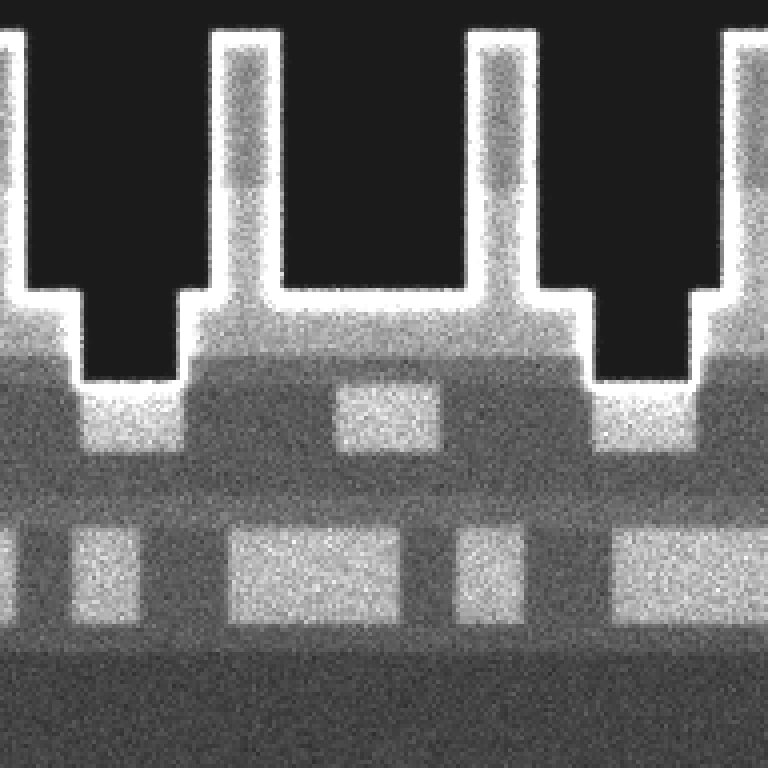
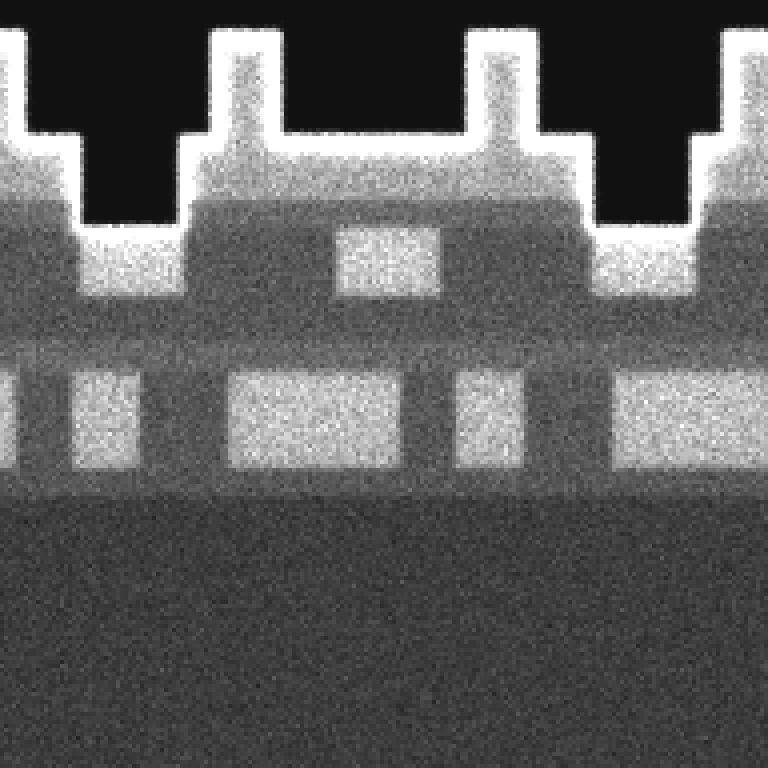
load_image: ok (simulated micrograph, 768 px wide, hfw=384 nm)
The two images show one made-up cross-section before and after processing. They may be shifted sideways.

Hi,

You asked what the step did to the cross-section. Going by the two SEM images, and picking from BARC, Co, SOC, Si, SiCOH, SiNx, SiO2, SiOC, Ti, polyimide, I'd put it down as SOC, removed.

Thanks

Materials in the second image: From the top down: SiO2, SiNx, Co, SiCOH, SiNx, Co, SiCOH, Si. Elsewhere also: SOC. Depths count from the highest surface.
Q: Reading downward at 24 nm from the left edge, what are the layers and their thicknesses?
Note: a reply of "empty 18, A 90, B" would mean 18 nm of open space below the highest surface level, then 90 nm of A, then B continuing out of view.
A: empty 52, SiO2 32, SiNx 14, SiCOH 56, SiNx 16, SiCOH 62, Si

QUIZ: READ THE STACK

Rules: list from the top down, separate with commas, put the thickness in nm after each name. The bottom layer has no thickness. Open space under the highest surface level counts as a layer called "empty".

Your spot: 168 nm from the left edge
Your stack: empty 52, SiO2 32, SiNx 14, Co 34, SiCOH 22, SiNx 16, Co 48, SiCOH 14, Si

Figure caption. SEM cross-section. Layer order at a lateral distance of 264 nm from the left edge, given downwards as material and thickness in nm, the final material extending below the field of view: SiO2 84, SiNx 14, SiCOH 56, SiNx 16, SiCOH 62, Si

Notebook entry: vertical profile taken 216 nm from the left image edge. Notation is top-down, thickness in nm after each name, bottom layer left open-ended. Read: empty 52, SiO2 32, SiNx 14, Co 34, SiCOH 22, SiNx 16, SiCOH 62, Si